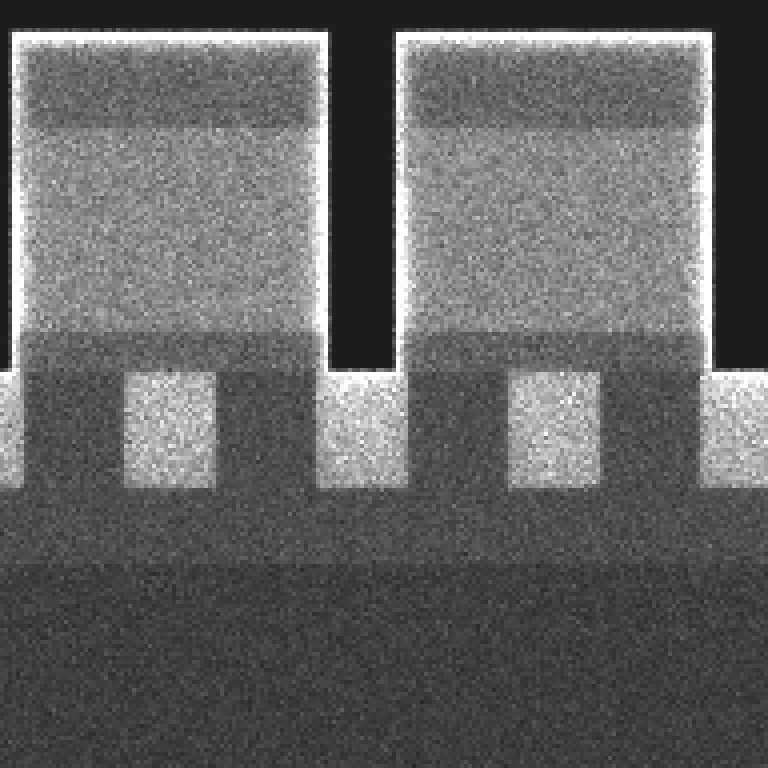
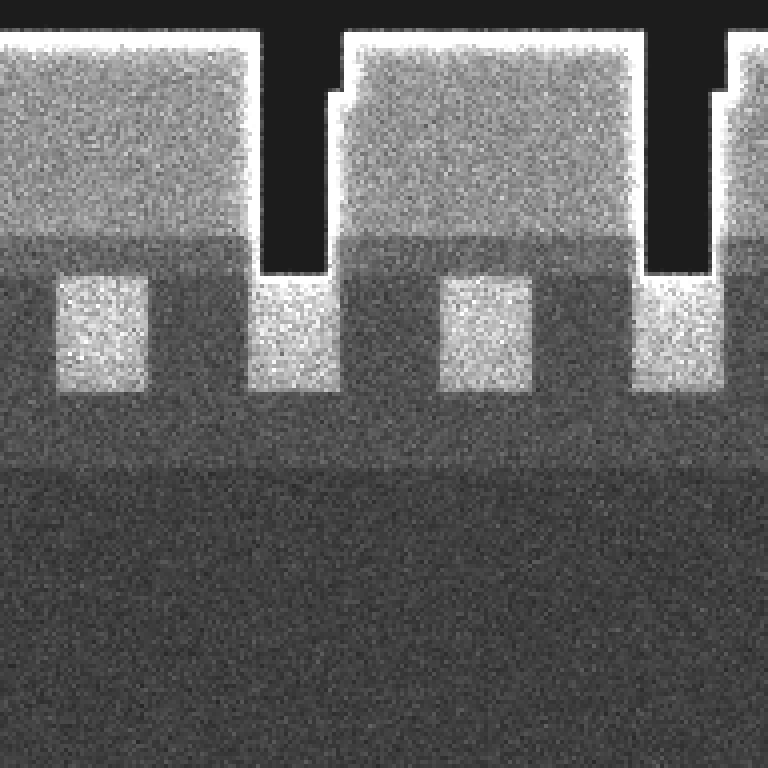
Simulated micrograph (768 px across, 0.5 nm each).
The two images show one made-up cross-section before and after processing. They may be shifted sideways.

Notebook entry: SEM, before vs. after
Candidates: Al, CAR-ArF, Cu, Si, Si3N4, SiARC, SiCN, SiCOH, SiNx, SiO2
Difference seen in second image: SiARC removed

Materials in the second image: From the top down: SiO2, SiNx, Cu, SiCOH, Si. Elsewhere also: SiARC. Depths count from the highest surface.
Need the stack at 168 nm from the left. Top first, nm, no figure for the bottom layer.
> empty 30, SiO2 72, SiNx 20, Cu 58, SiCOH 38, Si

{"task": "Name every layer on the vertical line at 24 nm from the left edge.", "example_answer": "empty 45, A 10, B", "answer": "SiO2 102, SiNx 20, SiCOH 96, Si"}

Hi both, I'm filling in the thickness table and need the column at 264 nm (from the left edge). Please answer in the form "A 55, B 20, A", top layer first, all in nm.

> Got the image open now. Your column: SiO2 102, SiNx 20, Cu 58, SiCOH 38, Si